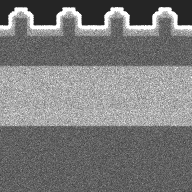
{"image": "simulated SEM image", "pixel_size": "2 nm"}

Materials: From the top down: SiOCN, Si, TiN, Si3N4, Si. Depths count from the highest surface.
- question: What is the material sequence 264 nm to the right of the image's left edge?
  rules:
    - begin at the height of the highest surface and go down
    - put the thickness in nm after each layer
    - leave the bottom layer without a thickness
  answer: empty 36, SiOCN 20, Si 60, TiN 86, Si3N4 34, Si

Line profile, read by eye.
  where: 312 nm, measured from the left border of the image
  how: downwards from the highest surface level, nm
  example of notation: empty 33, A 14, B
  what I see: empty 8, SiOCN 48, Si 60, TiN 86, Si3N4 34, Si